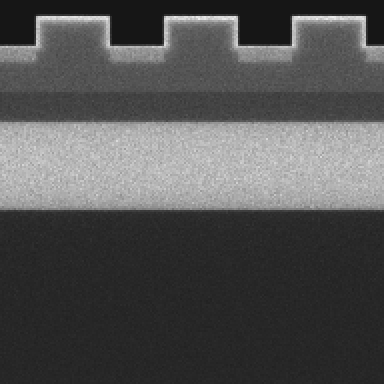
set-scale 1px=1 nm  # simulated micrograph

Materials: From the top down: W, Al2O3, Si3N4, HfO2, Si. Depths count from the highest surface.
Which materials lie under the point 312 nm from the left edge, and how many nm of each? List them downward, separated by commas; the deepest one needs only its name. Al2O3 76, Si3N4 30, HfO2 88, Si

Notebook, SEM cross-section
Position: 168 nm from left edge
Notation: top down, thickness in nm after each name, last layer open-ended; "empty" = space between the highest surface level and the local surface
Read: Al2O3 76, Si3N4 30, HfO2 88, Si